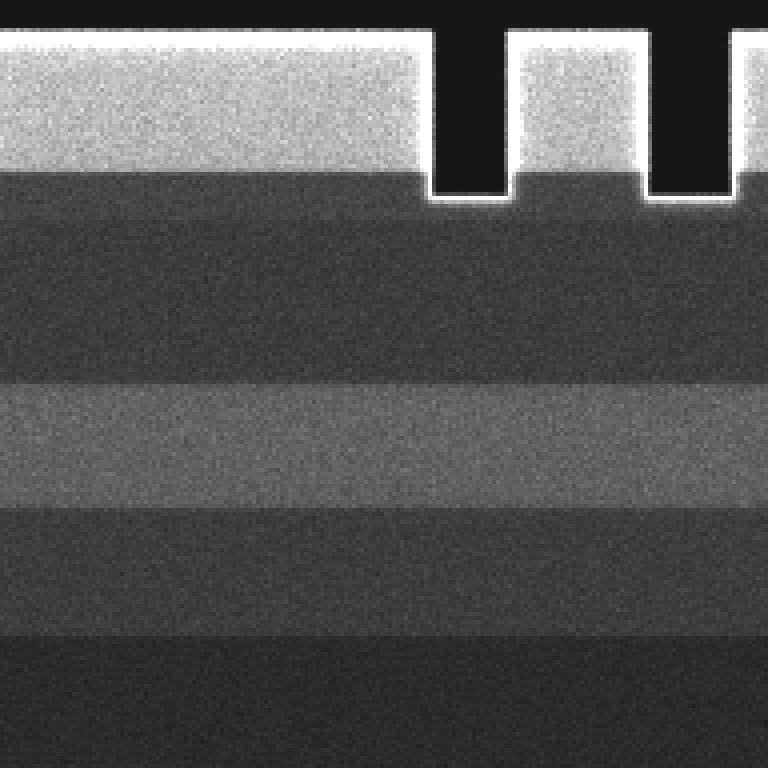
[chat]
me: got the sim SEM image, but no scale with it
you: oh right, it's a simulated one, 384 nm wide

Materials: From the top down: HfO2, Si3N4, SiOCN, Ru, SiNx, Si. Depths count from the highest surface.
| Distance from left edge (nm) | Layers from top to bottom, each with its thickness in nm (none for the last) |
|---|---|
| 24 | HfO2 70, Si3N4 24, SiOCN 82, Ru 62, SiNx 64, Si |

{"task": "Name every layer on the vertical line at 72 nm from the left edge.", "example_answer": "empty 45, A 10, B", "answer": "HfO2 70, Si3N4 24, SiOCN 82, Ru 62, SiNx 64, Si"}